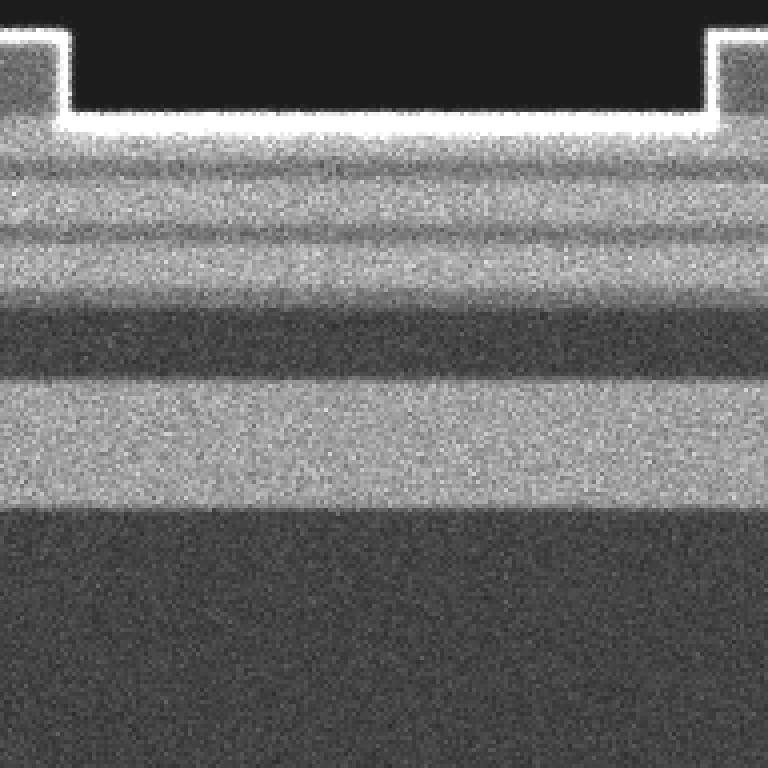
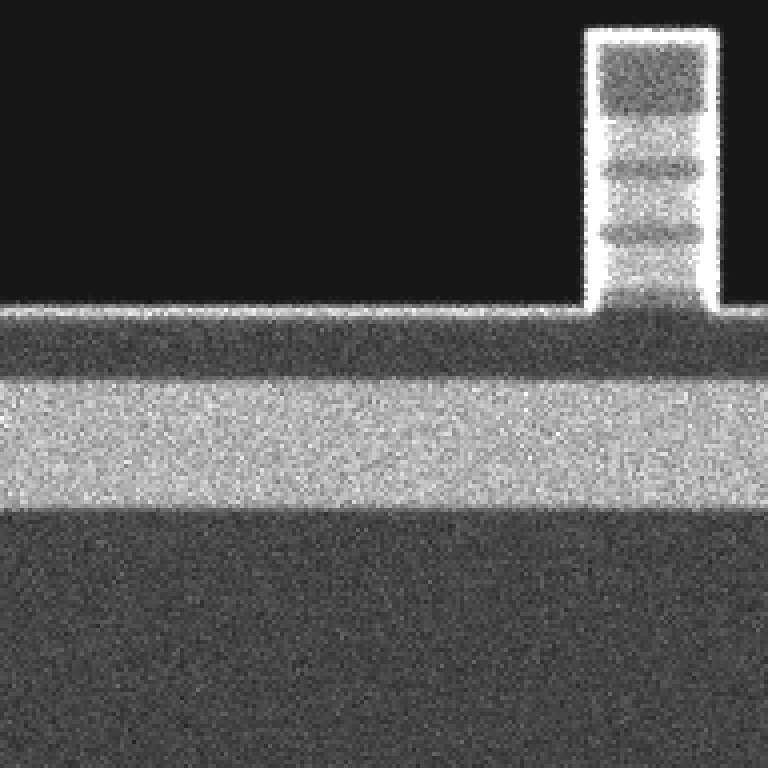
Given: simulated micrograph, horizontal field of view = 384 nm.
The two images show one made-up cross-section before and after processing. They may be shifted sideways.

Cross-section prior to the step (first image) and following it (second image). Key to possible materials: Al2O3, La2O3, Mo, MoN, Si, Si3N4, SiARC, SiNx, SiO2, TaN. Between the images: Al2O3 and Si3N4 was removed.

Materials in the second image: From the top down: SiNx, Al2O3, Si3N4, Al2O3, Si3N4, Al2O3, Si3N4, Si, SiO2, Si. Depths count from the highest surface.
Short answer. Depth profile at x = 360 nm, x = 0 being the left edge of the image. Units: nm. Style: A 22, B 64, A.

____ empty 138, Si 36, SiO2 64, Si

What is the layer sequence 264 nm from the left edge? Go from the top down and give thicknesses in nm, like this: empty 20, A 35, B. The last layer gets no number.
empty 138, Si 36, SiO2 64, Si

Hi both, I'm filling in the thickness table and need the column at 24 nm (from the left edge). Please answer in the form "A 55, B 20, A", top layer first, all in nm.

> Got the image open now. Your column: empty 138, Si 36, SiO2 64, Si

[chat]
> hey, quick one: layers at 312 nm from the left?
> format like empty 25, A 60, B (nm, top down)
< SiNx 42, Al2O3 22, Si3N4 10, Al2O3 22, Si3N4 10, Al2O3 22, Si3N4 10, Si 36, SiO2 64, Si